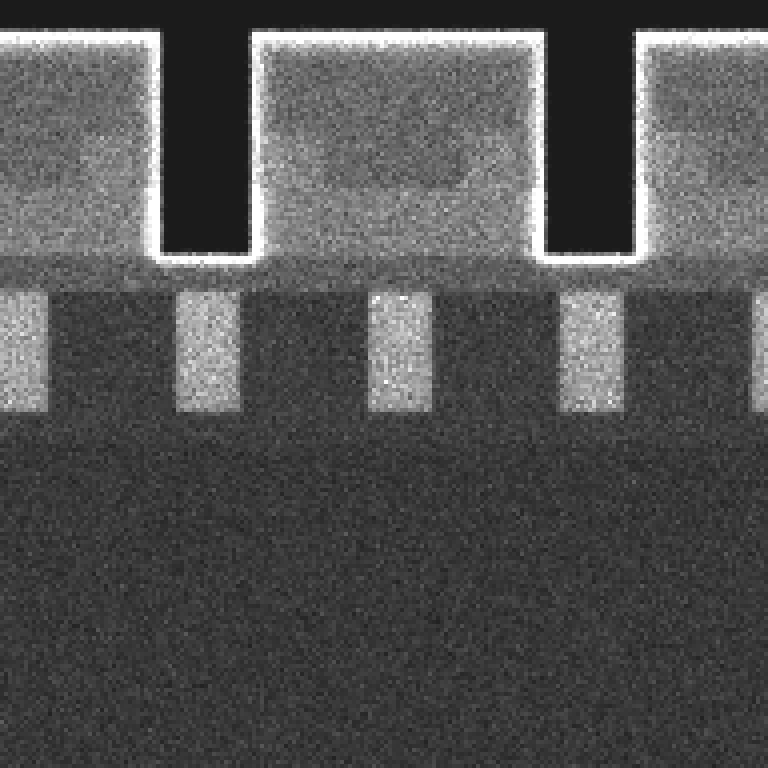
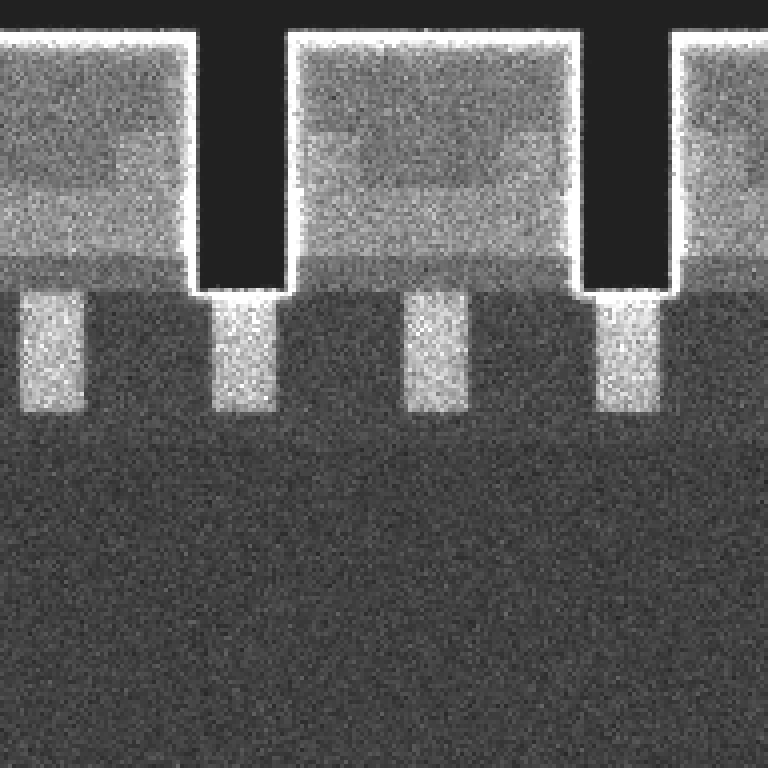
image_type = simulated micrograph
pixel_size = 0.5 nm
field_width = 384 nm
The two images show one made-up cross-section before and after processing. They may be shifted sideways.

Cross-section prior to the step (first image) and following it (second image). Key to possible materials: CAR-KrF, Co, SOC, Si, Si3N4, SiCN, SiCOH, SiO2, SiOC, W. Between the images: Si3N4 was removed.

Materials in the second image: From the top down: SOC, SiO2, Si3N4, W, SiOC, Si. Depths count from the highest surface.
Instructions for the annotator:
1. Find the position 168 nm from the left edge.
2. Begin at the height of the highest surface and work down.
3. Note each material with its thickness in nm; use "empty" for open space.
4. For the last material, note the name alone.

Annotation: SOC 50, SiO2 62, Si3N4 18, SiOC 76, Si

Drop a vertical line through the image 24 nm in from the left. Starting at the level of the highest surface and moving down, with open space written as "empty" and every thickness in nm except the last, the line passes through SOC 78, SiO2 34, Si3N4 18, W 60, SiOC 16, Si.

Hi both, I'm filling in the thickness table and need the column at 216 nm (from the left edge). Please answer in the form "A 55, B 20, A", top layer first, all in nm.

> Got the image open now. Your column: SOC 78, SiO2 34, Si3N4 18, W 60, SiOC 16, Si